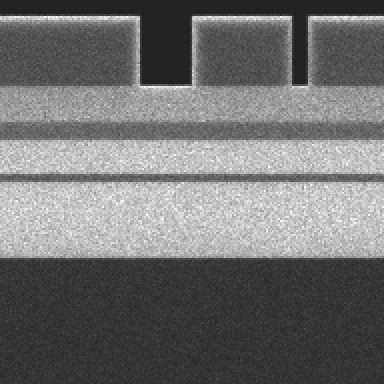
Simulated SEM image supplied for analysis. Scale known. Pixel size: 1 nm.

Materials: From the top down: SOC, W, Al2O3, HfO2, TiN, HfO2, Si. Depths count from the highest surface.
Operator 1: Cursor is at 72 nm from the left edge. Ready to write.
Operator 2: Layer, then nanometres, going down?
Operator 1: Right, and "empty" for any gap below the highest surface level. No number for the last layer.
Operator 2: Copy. SOC 70, W 36, Al2O3 18, HfO2 34, TiN 8, HfO2 76, Si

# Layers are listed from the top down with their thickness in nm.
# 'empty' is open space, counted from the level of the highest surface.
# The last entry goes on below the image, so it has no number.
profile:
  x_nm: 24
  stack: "SOC 70, W 36, Al2O3 18, HfO2 34, TiN 8, HfO2 76, Si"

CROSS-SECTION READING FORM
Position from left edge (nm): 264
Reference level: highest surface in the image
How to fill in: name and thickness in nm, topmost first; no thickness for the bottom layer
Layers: SOC 70, W 36, Al2O3 18, HfO2 34, TiN 8, HfO2 76, Si